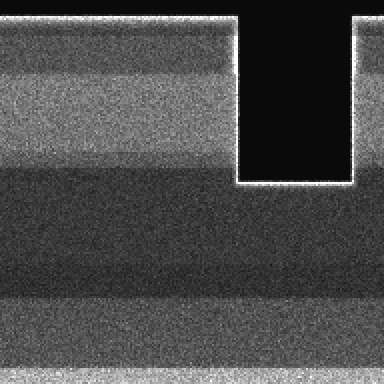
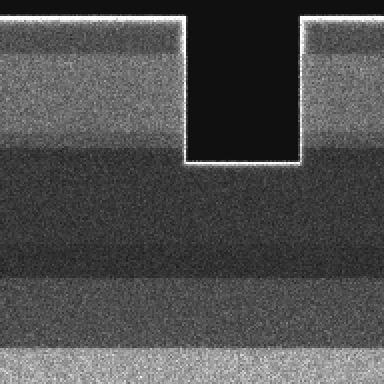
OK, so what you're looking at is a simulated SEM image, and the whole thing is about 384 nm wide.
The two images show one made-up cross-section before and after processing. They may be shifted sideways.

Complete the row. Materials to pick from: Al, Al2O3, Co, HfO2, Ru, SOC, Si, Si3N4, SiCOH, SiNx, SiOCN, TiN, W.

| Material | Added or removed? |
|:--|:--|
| SOC | removed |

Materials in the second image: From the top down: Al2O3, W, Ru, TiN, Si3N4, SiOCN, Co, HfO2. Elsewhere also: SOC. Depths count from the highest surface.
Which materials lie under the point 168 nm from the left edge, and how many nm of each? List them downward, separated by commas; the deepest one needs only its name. Al2O3 38, W 78, Ru 16, TiN 14, Si3N4 82, SiOCN 34, Co 70, HfO2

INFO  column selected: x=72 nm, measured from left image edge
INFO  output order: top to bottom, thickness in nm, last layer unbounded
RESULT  Al2O3 38, W 78, Ru 16, TiN 14, Si3N4 82, SiOCN 34, Co 70, HfO2